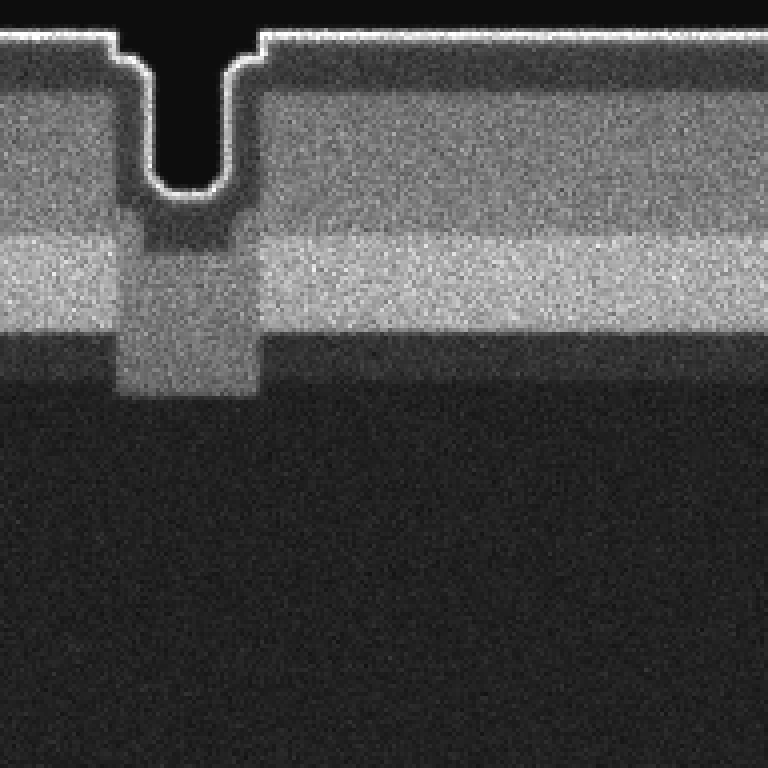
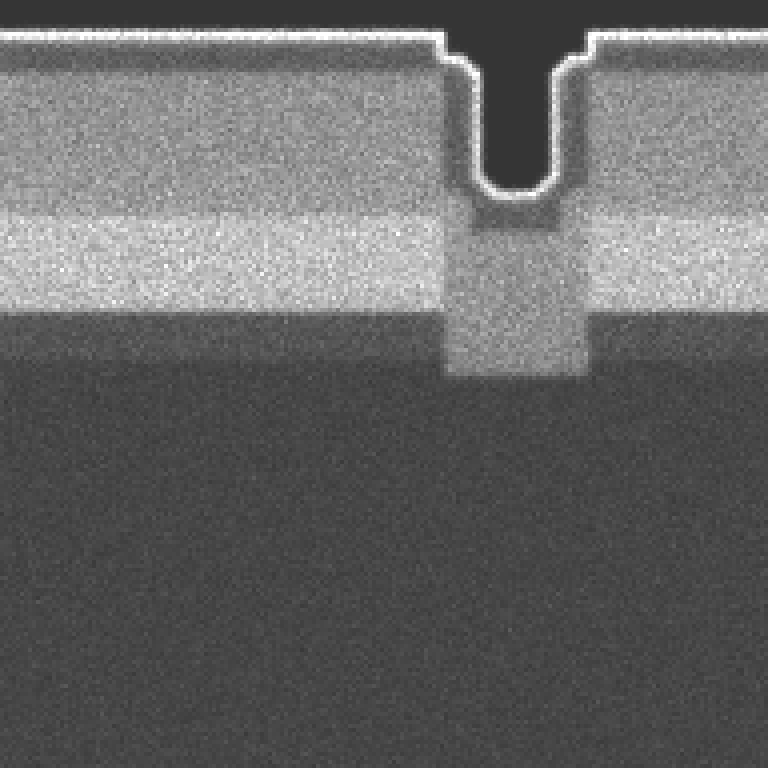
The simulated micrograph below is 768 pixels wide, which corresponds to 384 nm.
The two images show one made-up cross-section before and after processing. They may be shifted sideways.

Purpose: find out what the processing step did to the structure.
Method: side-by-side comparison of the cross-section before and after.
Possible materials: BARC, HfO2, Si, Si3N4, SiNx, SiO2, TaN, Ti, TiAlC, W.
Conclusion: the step removed Si3N4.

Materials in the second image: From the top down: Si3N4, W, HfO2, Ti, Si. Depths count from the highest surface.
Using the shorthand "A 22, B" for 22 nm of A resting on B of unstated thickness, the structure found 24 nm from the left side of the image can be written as Si3N4 20, W 72, HfO2 48, Ti 24, Si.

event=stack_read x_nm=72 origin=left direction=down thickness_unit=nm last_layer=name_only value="Si3N4 20, W 72, HfO2 48, Ti 24, Si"